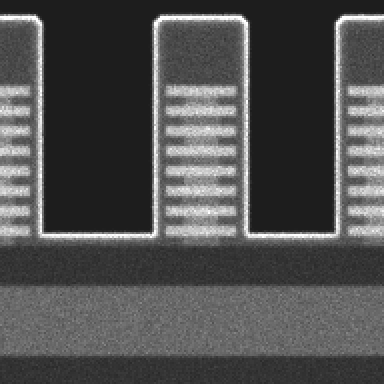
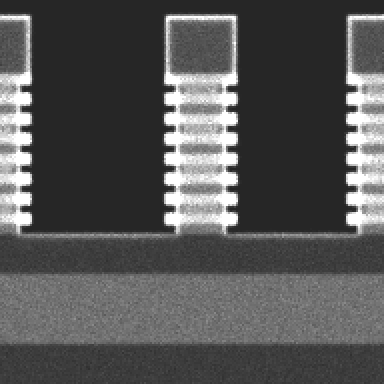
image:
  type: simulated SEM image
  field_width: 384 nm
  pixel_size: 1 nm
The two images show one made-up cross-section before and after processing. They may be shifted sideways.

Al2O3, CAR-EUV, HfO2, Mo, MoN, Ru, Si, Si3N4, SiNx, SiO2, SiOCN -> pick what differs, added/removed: Si3N4 removed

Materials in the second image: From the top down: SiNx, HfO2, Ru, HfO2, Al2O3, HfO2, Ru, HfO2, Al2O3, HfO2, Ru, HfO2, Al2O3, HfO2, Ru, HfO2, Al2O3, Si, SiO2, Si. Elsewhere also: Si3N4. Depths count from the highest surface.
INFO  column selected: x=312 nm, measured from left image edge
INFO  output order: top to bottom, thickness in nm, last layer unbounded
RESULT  empty 218, Si 40, SiO2 70, Si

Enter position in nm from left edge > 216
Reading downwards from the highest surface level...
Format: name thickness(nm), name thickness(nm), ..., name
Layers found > SiNx 58, HfO2 10, Ru 10, HfO2 10, Al2O3 10, HfO2 10, Ru 10, HfO2 10, Al2O3 10, HfO2 10, Ru 10, HfO2 10, Al2O3 10, HfO2 10, Ru 10, HfO2 10, Al2O3 10, Si 40, SiO2 70, Si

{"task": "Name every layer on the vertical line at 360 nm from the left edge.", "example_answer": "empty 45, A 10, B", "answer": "SiNx 58, HfO2 10, Si3N4 10, HfO2 10, Si3N4 10, HfO2 10, Si3N4 10, HfO2 10, Si3N4 10, HfO2 10, Si3N4 10, HfO2 10, Si3N4 10, HfO2 10, Si3N4 10, HfO2 10, Si3N4 10, Si 40, SiO2 70, Si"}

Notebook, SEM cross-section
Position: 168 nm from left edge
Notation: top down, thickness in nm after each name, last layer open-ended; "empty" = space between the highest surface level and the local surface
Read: SiNx 58, HfO2 10, empty 10, HfO2 10, empty 10, HfO2 10, empty 10, HfO2 10, empty 10, HfO2 10, empty 10, HfO2 10, empty 10, HfO2 10, empty 10, HfO2 10, empty 10, Si 40, SiO2 70, Si